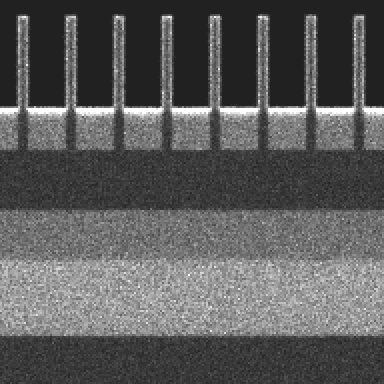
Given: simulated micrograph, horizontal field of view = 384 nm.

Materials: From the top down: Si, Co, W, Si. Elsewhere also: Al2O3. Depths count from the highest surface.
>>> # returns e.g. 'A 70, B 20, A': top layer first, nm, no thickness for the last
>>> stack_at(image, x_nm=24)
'Si 194, Co 50, W 76, Si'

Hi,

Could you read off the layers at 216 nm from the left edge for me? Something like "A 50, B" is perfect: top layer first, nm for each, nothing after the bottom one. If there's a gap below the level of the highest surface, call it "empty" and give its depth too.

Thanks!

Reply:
Si 194, Co 50, W 76, Si